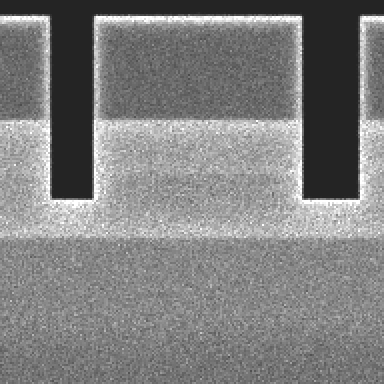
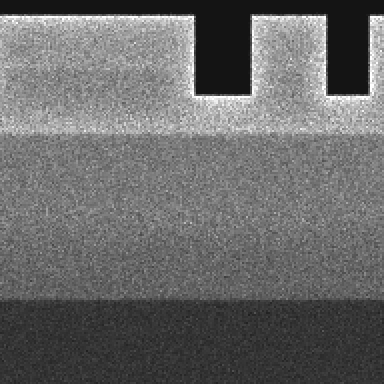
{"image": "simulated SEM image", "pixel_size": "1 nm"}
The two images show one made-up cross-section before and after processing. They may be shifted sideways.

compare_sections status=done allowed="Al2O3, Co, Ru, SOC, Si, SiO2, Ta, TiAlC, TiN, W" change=removed material="SOC"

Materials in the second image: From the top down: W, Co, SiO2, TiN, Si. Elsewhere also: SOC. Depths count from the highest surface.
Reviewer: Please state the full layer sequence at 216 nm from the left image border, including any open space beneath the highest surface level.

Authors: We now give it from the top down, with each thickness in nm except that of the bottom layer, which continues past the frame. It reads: empty 80, Co 38, SiO2 76, TiN 90, Si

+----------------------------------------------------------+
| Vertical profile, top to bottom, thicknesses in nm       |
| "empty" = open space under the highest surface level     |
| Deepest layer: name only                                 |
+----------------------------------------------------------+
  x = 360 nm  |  empty 80, Co 38, SiO2 76, TiN 90, Si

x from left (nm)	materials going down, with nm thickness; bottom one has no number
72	W 54, Co 64, SiO2 76, TiN 90, Si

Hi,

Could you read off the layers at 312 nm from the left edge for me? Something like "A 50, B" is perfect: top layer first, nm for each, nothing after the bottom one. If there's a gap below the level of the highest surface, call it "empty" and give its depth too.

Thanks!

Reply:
W 54, Co 64, SiO2 76, TiN 90, Si